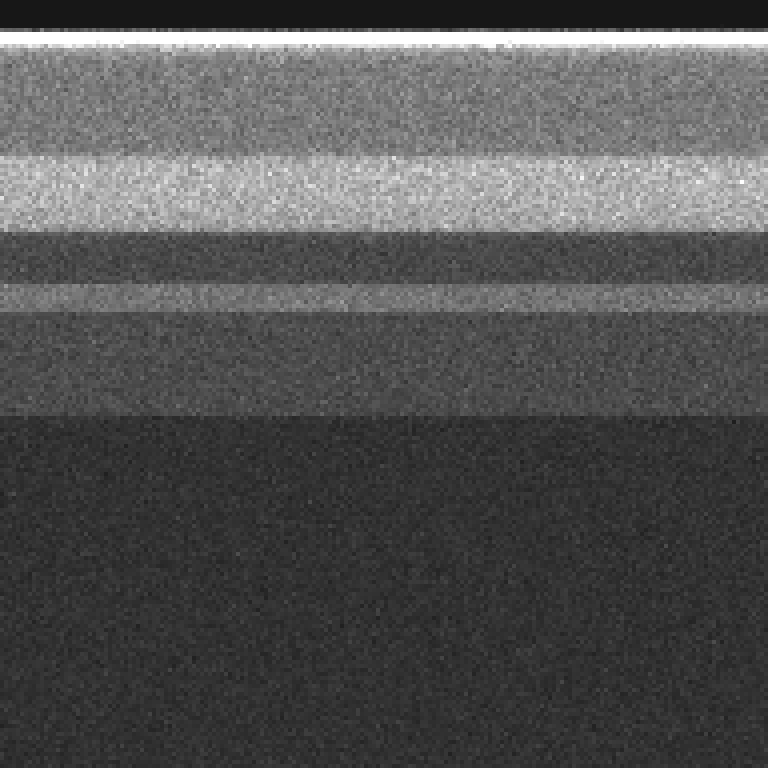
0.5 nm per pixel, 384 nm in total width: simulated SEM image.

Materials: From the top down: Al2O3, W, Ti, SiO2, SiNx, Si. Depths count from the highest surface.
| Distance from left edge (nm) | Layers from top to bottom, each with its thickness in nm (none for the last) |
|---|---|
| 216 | Al2O3 62, W 38, Ti 26, SiO2 14, SiNx 52, Si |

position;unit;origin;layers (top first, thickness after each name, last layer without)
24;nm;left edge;Al2O3 62, W 38, Ti 26, SiO2 14, SiNx 52, Si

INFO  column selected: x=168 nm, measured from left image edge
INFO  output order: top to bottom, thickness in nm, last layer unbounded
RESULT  Al2O3 62, W 38, Ti 26, SiO2 14, SiNx 52, Si